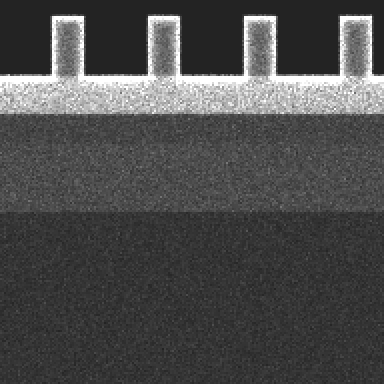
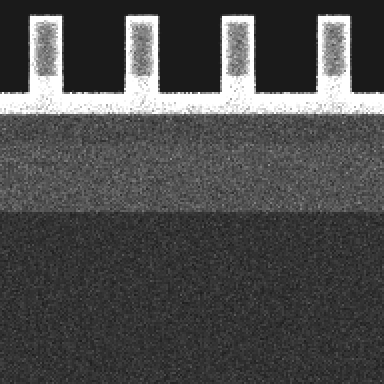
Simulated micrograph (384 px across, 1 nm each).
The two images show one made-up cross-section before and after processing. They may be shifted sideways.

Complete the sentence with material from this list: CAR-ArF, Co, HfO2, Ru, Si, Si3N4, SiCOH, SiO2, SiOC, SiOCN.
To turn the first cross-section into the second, HfO2 must be removed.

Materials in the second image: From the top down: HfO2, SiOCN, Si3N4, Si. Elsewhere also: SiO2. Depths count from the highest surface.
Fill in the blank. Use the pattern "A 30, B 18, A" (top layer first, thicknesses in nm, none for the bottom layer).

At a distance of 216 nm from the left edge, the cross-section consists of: empty 78, HfO2 20, SiOCN 30, Si3N4 68, Si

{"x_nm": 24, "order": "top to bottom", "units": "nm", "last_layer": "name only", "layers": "empty 78, HfO2 20, SiOCN 30, Si3N4 68, Si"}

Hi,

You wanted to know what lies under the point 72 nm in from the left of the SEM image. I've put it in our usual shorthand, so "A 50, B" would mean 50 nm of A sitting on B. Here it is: empty 78, HfO2 20, SiOCN 30, Si3N4 68, Si